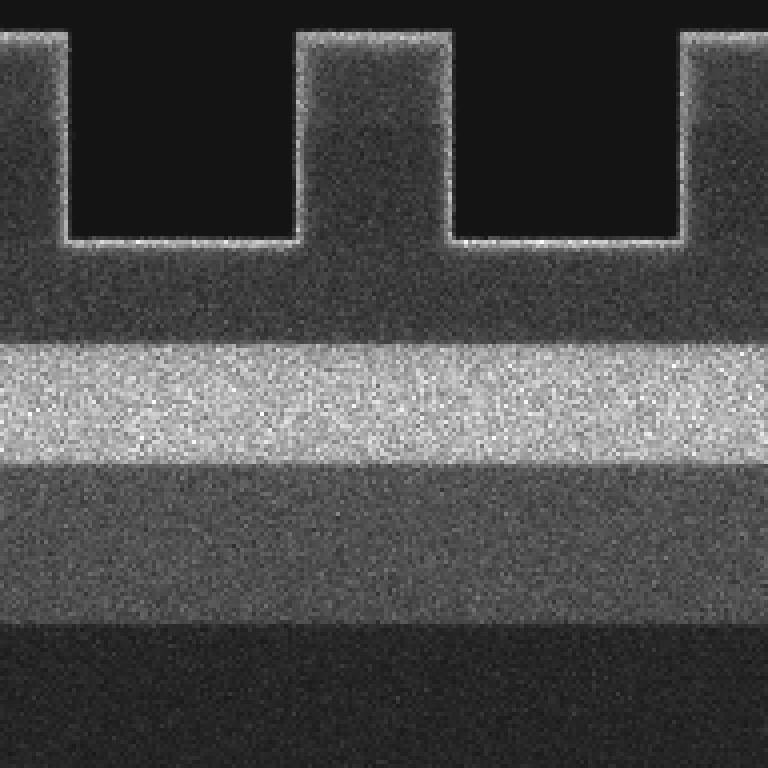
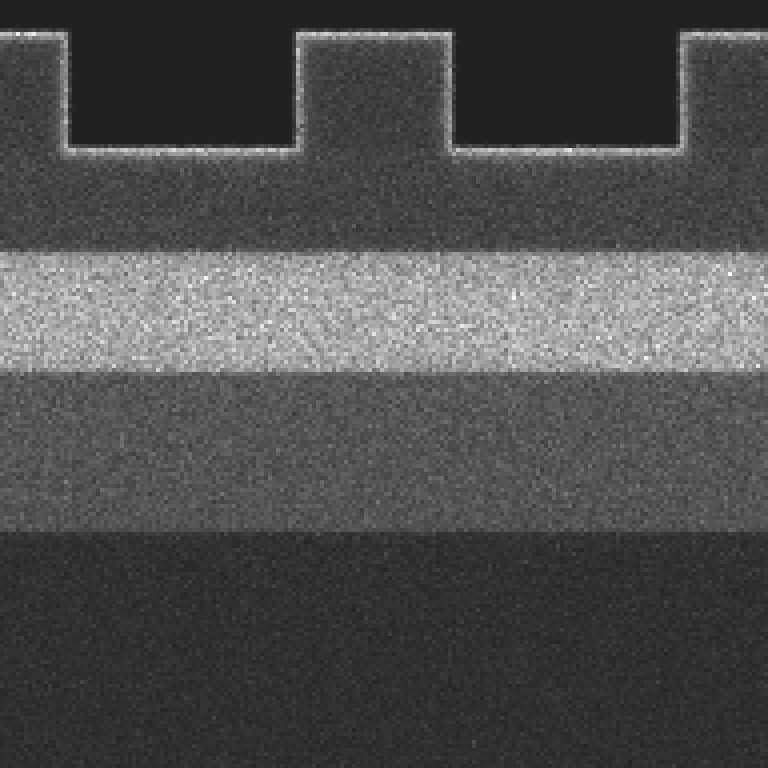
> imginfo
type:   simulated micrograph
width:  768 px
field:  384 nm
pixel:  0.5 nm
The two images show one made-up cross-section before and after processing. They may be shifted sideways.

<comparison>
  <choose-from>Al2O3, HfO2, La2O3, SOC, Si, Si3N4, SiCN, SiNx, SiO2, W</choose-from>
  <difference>SOC removed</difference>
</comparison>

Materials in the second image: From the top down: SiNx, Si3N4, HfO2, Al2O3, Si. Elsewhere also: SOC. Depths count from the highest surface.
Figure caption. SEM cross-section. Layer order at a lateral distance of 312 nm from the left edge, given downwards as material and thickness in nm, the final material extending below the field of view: empty 58, Si3N4 52, HfO2 60, Al2O3 80, Si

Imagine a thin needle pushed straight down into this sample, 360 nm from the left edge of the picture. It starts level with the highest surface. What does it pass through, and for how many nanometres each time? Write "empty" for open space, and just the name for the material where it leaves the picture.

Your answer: SiNx 58, Si3N4 52, HfO2 60, Al2O3 80, Si